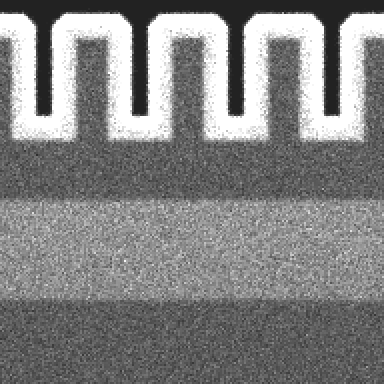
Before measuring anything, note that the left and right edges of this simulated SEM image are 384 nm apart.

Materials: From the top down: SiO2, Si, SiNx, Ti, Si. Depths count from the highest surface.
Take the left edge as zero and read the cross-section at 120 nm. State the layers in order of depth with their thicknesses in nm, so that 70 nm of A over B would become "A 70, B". empty 2, SiO2 122, Si 60, SiNx 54, Ti 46, Si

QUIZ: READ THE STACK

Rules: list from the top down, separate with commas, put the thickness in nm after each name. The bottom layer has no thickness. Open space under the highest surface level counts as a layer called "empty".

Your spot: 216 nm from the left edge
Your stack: empty 2, SiO2 122, Si 60, SiNx 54, Ti 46, Si